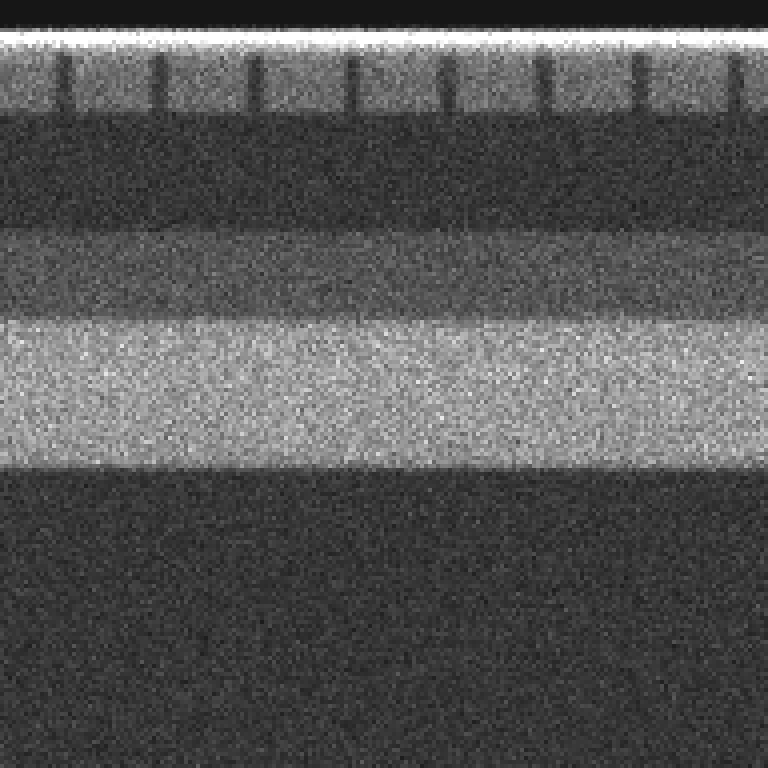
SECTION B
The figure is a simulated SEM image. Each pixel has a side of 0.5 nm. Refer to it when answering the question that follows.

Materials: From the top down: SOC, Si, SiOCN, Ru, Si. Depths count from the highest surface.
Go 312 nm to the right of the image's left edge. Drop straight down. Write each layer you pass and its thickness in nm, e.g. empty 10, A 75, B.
SOC 40, Si 60, SiOCN 44, Ru 74, Si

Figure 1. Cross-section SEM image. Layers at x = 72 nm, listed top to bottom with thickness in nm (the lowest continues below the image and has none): SOC 40, Si 60, SiOCN 44, Ru 74, Si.